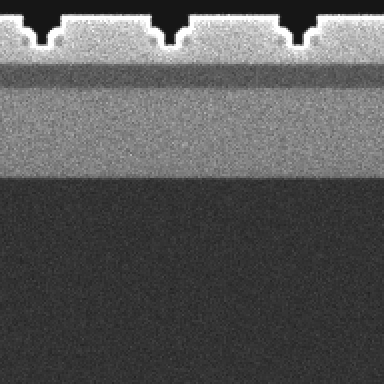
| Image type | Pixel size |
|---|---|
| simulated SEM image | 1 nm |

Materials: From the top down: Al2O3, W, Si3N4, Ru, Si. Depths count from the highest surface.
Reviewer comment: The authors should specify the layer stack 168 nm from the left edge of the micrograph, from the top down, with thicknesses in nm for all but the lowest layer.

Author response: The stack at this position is empty 30, W 18, Si3N4 24, Ru 90, Si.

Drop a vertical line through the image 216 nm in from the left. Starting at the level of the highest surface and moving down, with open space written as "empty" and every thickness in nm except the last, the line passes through W 48, Si3N4 24, Ru 90, Si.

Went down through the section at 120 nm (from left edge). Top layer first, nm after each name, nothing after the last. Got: W 48, Si3N4 24, Ru 90, Si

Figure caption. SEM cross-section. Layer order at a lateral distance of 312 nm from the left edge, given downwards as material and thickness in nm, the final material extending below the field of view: empty 12, Al2O3 18, W 18, Si3N4 24, Ru 90, Si